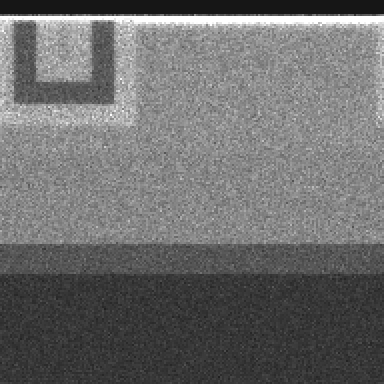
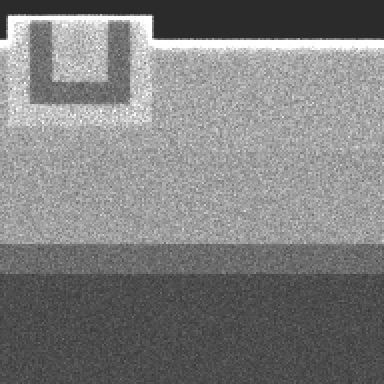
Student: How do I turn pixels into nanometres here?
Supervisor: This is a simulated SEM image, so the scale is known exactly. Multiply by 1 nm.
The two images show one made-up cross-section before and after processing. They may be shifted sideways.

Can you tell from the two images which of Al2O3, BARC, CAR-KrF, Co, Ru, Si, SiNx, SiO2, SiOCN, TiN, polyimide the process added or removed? Yes, it removed Al2O3.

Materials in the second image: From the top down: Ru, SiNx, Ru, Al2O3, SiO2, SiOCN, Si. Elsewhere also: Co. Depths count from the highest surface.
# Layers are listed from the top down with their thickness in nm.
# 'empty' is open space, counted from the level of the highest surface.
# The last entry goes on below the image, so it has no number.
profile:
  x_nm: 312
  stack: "empty 24, Al2O3 112, SiO2 92, SiOCN 30, Si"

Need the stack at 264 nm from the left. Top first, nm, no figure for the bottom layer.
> empty 24, Al2O3 112, SiO2 92, SiOCN 30, Si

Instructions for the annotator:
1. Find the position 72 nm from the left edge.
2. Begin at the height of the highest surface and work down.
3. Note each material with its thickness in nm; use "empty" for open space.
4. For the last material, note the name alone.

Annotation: Ru 66, SiNx 22, Ru 22, Al2O3 26, SiO2 92, SiOCN 30, Si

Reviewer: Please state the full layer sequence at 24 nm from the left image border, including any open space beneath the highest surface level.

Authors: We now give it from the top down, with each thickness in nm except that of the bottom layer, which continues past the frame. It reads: Ru 110, Al2O3 26, SiO2 92, SiOCN 30, Si